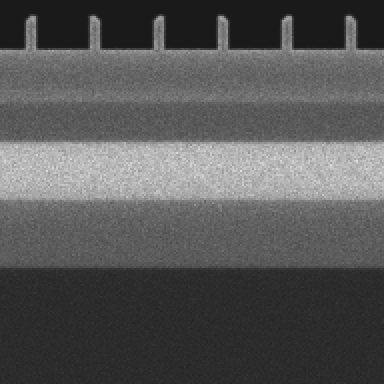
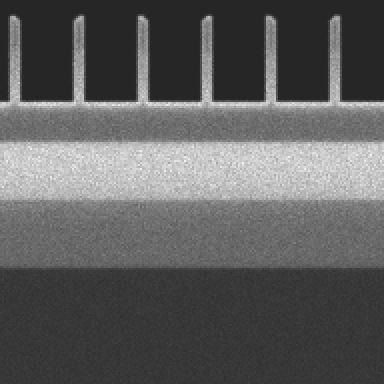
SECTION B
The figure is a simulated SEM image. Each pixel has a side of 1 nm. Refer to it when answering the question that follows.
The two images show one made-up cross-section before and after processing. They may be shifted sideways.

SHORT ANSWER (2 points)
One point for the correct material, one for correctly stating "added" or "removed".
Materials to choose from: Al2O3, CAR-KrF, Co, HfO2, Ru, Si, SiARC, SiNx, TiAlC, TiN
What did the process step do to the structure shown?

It removed Ru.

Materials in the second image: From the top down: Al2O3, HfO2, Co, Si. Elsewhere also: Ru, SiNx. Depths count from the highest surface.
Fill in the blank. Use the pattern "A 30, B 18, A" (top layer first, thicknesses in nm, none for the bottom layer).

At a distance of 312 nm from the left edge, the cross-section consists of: empty 86, Al2O3 40, HfO2 58, Co 68, Si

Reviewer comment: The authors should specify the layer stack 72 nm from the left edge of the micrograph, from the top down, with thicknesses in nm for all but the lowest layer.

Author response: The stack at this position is empty 86, Al2O3 40, HfO2 58, Co 68, Si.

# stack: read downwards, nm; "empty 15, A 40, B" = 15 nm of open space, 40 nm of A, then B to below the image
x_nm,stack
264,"empty 86, Al2O3 40, HfO2 58, Co 68, Si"